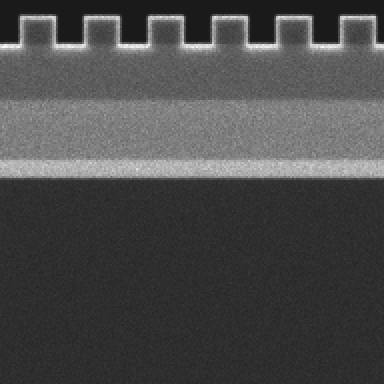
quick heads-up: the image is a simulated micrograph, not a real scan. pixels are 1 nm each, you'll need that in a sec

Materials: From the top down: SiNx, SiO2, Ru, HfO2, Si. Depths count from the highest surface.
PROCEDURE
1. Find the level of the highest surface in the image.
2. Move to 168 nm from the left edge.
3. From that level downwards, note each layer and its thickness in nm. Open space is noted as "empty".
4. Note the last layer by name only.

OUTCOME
SiNx 28, SiO2 56, Ru 60, HfO2 18, Si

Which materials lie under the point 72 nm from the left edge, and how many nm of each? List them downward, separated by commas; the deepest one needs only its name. empty 28, SiO2 56, Ru 60, HfO2 18, Si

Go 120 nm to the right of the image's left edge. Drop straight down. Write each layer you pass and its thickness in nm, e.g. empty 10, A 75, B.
empty 28, SiO2 56, Ru 60, HfO2 18, Si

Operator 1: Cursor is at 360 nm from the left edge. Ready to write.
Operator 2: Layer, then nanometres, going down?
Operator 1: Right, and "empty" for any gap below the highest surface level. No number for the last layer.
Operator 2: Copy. SiNx 28, SiO2 56, Ru 60, HfO2 18, Si